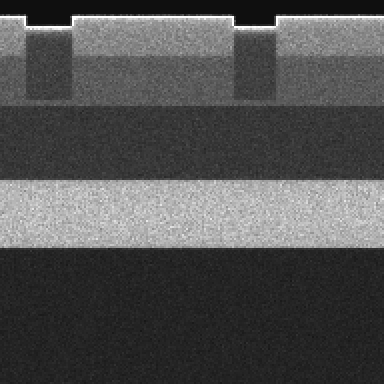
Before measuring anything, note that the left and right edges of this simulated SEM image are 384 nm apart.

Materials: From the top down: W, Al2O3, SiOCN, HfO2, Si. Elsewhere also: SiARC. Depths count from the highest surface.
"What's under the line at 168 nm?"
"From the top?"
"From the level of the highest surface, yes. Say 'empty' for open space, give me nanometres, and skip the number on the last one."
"W 40, Al2O3 50, SiOCN 74, HfO2 68, Si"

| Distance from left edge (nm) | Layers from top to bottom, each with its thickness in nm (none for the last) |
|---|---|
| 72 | W 40, Al2O3 50, SiOCN 74, HfO2 68, Si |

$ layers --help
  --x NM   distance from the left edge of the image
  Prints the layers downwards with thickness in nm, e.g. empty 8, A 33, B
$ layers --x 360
W 40, Al2O3 50, SiOCN 74, HfO2 68, Si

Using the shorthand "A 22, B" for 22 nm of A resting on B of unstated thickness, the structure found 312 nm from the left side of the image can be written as W 40, Al2O3 50, SiOCN 74, HfO2 68, Si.